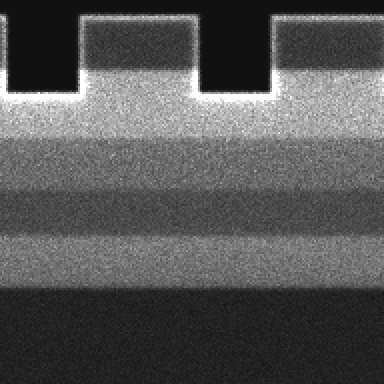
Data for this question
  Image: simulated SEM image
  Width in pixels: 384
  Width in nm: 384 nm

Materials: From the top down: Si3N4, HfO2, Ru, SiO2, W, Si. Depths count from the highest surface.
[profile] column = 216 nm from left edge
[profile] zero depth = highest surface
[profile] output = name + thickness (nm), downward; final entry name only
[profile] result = empty 78, HfO2 44, Ru 52, SiO2 46, W 52, Si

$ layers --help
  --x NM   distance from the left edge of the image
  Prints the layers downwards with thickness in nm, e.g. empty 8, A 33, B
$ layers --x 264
empty 78, HfO2 44, Ru 52, SiO2 46, W 52, Si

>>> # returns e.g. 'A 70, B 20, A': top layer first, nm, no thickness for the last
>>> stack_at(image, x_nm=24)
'empty 78, HfO2 44, Ru 52, SiO2 46, W 52, Si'